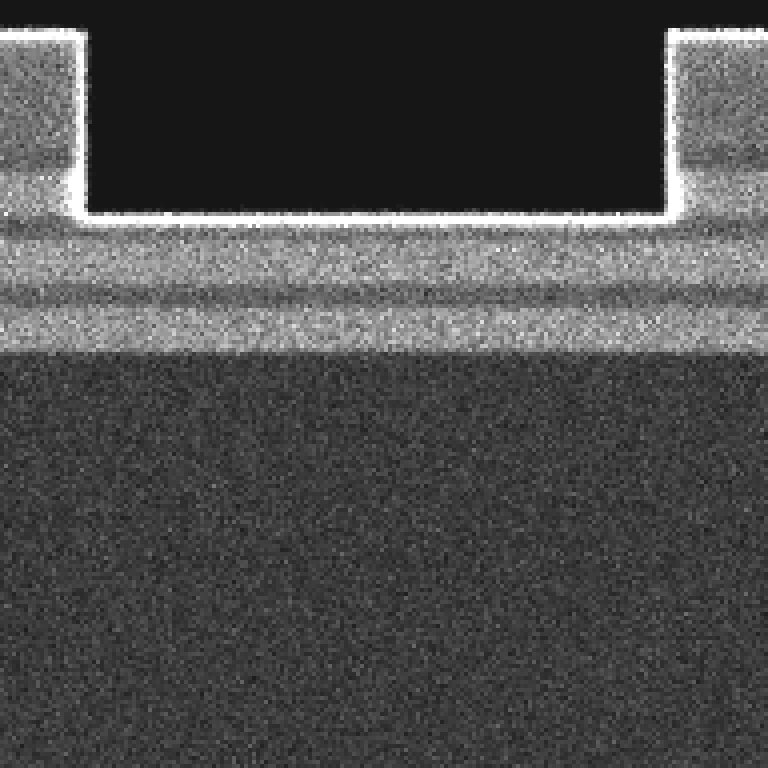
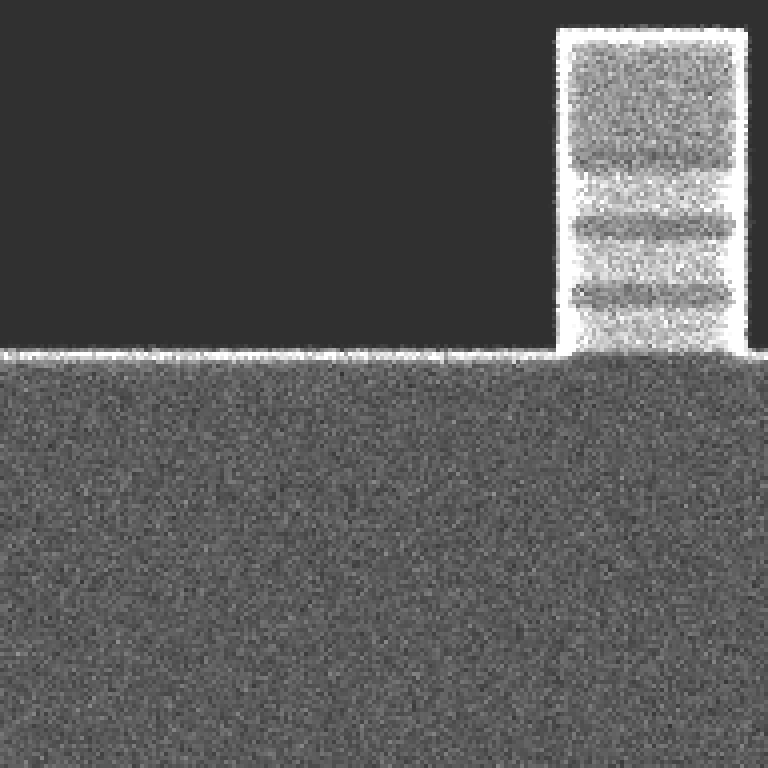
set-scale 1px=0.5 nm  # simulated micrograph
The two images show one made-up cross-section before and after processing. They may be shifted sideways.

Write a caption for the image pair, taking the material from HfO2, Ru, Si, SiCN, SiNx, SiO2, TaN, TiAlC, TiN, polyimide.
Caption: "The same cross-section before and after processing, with SiNx and SiO2 removed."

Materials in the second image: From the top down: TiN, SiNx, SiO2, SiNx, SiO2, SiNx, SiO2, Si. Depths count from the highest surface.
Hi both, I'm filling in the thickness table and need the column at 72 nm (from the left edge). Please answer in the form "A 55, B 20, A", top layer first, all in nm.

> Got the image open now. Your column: empty 160, Si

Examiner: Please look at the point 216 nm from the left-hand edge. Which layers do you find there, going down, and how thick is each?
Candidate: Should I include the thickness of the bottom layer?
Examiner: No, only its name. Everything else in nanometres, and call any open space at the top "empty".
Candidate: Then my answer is empty 160, Si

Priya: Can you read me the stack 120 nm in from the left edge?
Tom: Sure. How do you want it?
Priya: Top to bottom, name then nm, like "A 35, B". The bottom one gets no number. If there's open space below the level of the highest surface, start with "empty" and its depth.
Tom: empty 160, Si